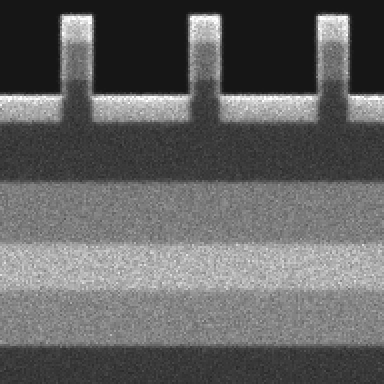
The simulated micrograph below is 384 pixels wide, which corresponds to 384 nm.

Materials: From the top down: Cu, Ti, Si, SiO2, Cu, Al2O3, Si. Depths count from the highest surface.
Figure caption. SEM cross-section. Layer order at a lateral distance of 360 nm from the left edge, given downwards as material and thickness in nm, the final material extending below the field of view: empty 80, Cu 26, Si 60, SiO2 62, Cu 46, Al2O3 56, Si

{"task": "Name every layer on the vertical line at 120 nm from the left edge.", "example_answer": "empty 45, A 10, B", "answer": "empty 80, Cu 26, Si 60, SiO2 62, Cu 46, Al2O3 56, Si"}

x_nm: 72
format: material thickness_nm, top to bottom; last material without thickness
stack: Cu 26, Ti 38, Si 102, SiO2 62, Cu 46, Al2O3 56, Si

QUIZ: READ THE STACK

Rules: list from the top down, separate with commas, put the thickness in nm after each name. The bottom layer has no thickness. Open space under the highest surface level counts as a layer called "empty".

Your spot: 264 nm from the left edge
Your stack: empty 80, Cu 26, Si 60, SiO2 62, Cu 46, Al2O3 56, Si